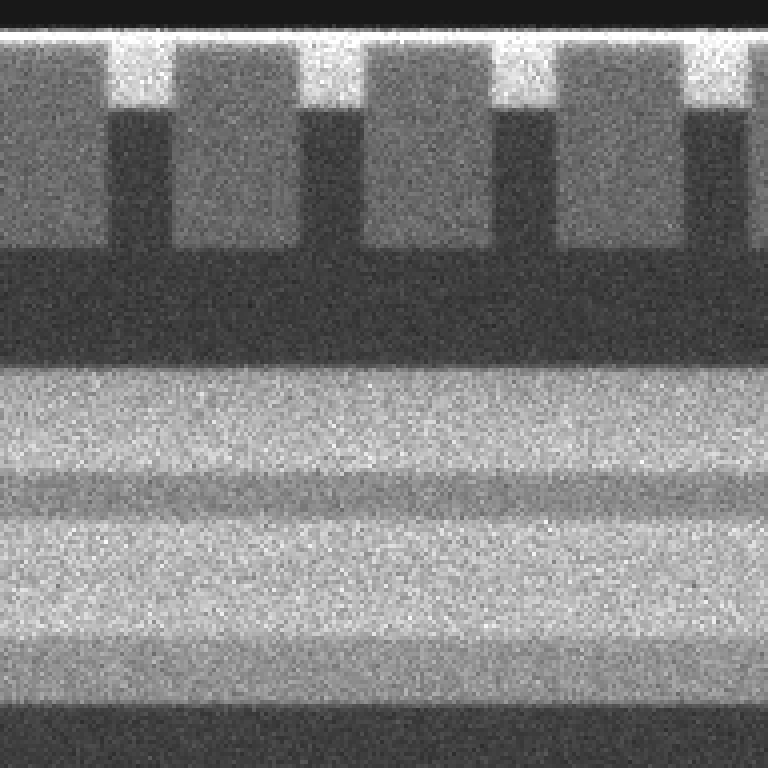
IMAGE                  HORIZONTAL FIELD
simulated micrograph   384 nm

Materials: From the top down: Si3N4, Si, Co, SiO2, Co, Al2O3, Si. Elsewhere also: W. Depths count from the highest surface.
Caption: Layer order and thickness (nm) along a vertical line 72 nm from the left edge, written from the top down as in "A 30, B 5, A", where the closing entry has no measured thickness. W 38, Si 130, Co 52, SiO2 24, Co 58, Al2O3 34, Si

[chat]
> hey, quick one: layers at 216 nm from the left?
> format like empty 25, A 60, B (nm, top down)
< Si3N4 108, Si 60, Co 52, SiO2 24, Co 58, Al2O3 34, Si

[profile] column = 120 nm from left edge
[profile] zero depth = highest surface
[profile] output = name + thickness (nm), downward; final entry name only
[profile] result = Si3N4 108, Si 60, Co 52, SiO2 24, Co 58, Al2O3 34, Si